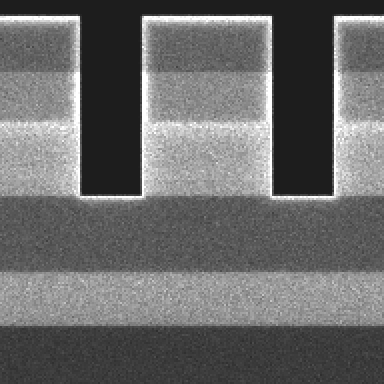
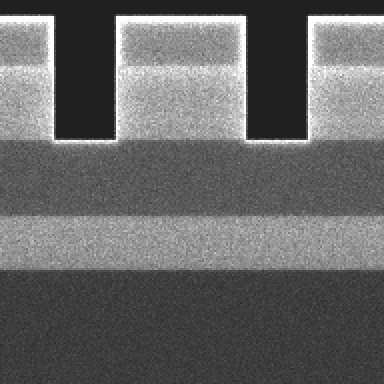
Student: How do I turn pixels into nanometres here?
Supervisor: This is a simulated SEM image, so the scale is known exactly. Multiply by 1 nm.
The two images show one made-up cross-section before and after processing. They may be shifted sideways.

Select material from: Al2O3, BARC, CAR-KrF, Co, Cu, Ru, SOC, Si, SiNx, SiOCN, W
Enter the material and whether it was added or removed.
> SOC / removed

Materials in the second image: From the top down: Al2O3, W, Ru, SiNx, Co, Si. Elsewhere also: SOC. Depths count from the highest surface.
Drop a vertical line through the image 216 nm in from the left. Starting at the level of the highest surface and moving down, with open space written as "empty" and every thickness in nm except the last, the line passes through Al2O3 50, W 58, Ru 16, SiNx 76, Co 54, Si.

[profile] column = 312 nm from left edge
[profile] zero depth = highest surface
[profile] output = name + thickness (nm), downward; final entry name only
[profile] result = Al2O3 50, W 58, Ru 16, SiNx 76, Co 54, Si